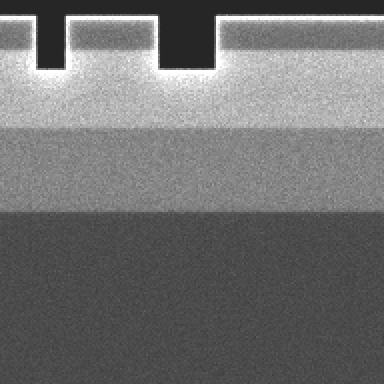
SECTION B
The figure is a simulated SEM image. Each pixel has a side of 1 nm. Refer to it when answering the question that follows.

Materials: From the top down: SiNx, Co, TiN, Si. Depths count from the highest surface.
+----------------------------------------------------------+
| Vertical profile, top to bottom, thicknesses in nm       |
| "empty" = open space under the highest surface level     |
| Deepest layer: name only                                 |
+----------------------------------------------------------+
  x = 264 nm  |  SiNx 34, Co 78, TiN 84, Si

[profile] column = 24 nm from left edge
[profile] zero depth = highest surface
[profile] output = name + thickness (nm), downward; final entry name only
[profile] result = SiNx 34, Co 78, TiN 84, Si